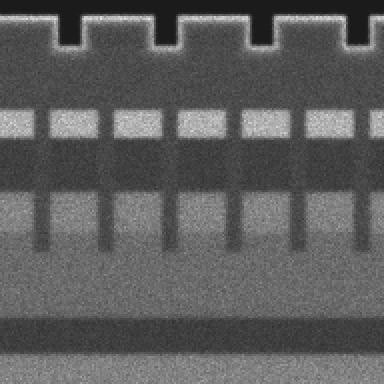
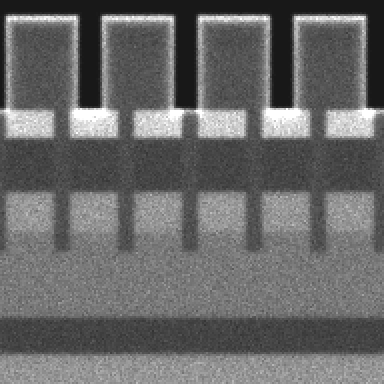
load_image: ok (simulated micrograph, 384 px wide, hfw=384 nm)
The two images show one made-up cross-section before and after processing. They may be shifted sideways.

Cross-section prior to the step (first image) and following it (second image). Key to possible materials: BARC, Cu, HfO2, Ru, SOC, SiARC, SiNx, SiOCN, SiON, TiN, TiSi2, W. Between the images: SOC was removed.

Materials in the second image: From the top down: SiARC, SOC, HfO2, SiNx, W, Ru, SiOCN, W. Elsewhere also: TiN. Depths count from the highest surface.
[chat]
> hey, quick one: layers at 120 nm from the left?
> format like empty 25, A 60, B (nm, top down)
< SiARC 30, SOC 64, TiN 142, Ru 66, SiOCN 36, W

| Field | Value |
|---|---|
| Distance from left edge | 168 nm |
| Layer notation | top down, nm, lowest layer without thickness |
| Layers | SiARC 30, SOC 64, HfO2 28, SiNx 54, W 40, Ru 86, SiOCN 36, W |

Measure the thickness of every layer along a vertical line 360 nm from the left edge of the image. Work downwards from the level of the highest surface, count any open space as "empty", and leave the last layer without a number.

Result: SiARC 30, SOC 64, HfO2 28, SiNx 54, W 40, Ru 86, SiOCN 36, W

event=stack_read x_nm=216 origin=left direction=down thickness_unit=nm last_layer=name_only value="SiARC 30, SOC 64, HfO2 28, SiNx 54, W 40, Ru 86, SiOCN 36, W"